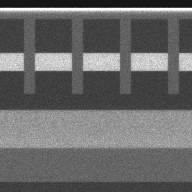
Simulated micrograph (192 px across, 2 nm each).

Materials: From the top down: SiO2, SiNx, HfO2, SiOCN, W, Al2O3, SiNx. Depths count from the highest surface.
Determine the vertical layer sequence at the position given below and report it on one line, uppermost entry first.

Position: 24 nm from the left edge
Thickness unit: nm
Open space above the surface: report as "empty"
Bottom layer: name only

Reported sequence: SiO2 22, SiNx 68, HfO2 36, SiOCN 78, W 76, Al2O3 68, SiNx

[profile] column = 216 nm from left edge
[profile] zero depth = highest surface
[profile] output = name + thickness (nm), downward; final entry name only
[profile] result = SiO2 22, SiNx 68, HfO2 36, SiOCN 78, W 76, Al2O3 68, SiNx